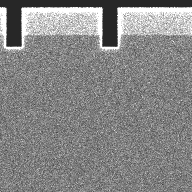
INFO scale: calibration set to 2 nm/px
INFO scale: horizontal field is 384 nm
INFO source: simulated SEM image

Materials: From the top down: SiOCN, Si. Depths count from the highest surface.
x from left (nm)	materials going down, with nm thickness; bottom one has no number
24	empty 78, Si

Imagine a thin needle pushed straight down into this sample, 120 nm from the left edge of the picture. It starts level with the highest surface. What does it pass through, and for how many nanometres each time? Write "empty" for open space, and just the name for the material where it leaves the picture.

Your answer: SiOCN 54, Si